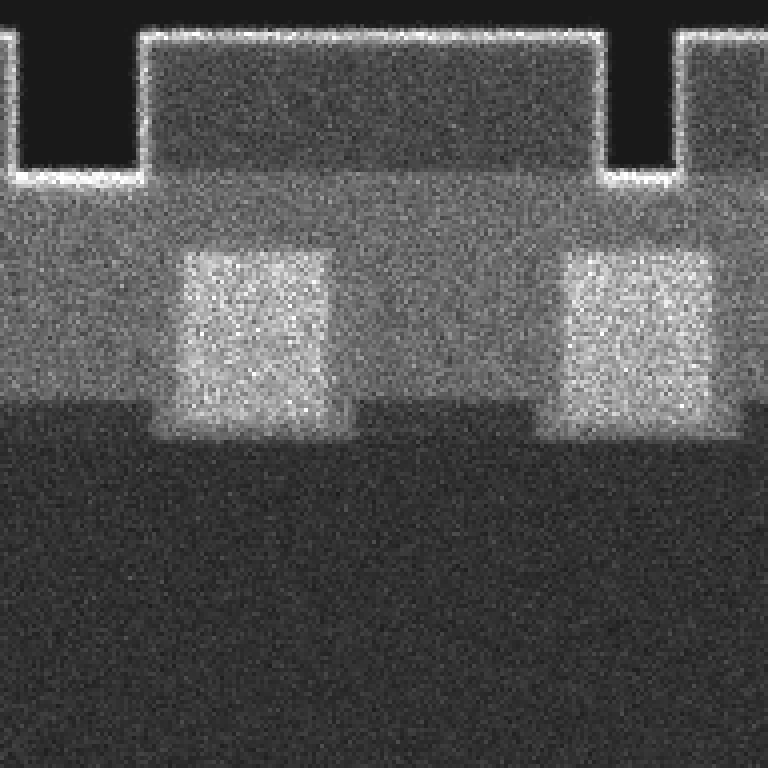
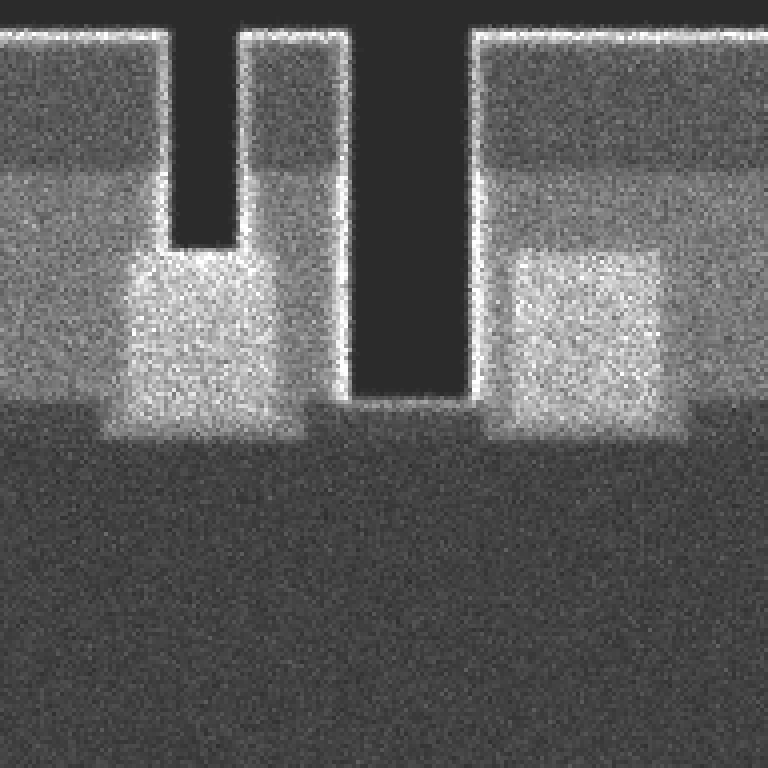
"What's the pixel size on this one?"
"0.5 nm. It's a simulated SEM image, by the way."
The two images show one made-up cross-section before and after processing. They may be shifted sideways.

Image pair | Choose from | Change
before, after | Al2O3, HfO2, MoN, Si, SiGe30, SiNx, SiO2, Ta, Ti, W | SiO2 (removed)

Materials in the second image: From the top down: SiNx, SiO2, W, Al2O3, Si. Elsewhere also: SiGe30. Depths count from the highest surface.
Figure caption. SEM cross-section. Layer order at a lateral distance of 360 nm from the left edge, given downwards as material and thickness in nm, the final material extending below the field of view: SiNx 70, SiO2 114, SiGe30 20, Si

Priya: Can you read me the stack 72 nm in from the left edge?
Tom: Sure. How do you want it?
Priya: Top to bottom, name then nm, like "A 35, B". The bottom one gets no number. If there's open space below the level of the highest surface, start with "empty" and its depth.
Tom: SiNx 70, SiO2 40, W 86, Al2O3 8, Si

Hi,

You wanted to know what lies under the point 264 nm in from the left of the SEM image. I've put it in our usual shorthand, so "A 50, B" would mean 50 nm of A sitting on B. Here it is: SiNx 70, SiO2 40, W 86, Al2O3 8, Si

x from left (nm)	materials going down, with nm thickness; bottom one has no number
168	SiNx 70, SiO2 114, SiGe30 20, Si